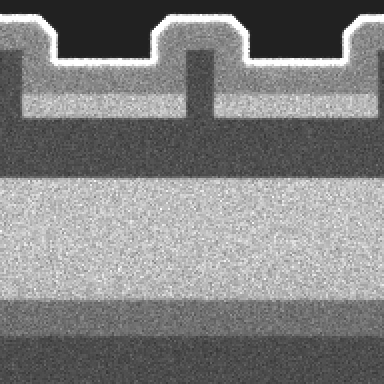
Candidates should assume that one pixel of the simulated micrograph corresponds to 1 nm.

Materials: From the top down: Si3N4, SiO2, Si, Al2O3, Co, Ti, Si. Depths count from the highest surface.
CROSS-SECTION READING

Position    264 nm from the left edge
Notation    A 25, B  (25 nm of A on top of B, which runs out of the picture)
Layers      empty 44, Si3N4 34, SiO2 24, Si 60, Al2O3 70, Co 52, Ti 36, Si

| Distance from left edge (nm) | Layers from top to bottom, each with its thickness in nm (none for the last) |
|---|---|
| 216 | Si3N4 78, SiO2 24, Si 60, Al2O3 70, Co 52, Ti 36, Si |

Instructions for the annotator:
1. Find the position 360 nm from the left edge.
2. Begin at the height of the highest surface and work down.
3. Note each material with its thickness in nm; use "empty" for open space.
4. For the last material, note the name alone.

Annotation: Si3N4 78, SiO2 24, Si 60, Al2O3 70, Co 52, Ti 36, Si